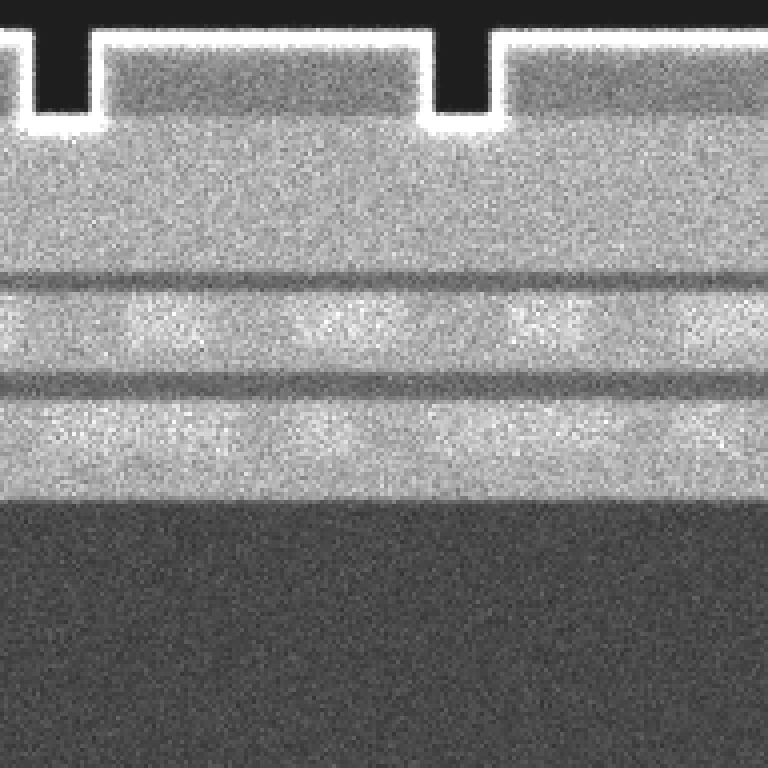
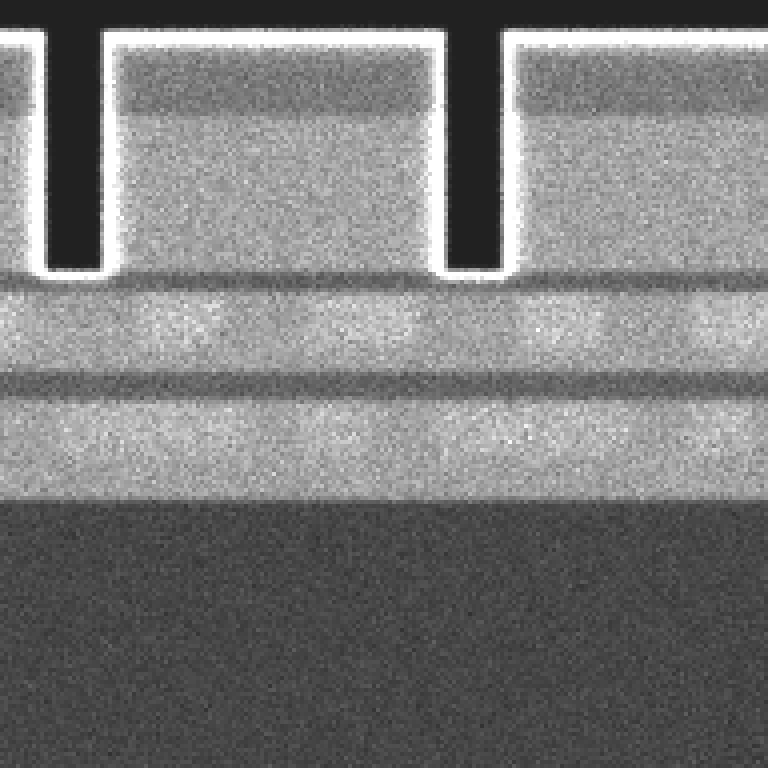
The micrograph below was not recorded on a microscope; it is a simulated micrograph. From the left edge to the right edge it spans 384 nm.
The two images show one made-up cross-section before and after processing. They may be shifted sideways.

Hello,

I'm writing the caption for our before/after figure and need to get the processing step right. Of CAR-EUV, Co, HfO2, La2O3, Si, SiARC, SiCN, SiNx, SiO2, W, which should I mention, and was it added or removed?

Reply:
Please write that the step removed SiO2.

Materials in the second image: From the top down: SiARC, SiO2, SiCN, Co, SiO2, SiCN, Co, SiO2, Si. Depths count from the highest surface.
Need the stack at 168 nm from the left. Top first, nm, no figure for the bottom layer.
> SiARC 42, SiO2 78, SiCN 10, Co 28, SiO2 12, SiCN 14, Co 28, SiO2 22, Si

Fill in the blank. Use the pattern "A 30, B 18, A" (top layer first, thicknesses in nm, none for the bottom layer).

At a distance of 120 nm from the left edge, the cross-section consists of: SiARC 42, SiO2 78, SiCN 10, SiO2 40, SiCN 14, Co 28, SiO2 22, Si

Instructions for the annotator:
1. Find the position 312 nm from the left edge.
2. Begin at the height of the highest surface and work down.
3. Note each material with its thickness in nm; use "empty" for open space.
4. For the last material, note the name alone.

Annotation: SiARC 42, SiO2 78, SiCN 10, SiO2 40, SiCN 14, Co 28, SiO2 22, Si